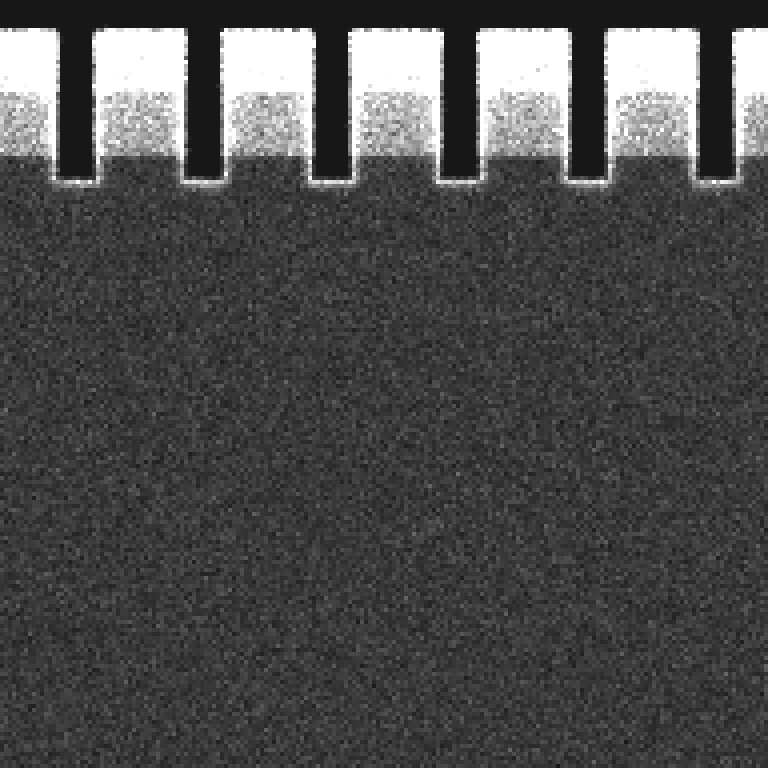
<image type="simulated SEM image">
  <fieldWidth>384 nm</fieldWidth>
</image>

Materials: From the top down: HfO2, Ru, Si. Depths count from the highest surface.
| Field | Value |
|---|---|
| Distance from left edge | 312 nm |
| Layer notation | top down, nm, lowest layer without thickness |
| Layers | HfO2 30, Ru 32, Si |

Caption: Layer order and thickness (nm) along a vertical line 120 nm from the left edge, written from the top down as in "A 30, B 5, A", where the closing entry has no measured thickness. HfO2 30, Ru 32, Si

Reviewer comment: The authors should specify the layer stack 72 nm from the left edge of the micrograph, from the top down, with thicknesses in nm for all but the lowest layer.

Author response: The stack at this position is HfO2 30, Ru 32, Si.